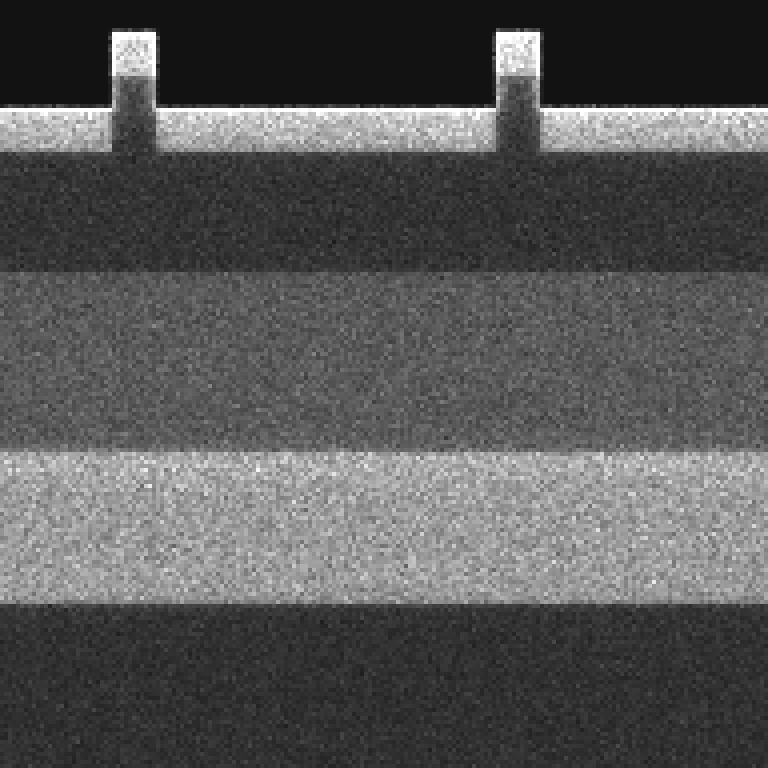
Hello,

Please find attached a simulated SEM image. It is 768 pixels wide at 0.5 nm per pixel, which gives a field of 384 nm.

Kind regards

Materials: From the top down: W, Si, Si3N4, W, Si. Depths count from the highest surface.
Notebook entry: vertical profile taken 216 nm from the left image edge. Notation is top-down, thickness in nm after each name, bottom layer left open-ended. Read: empty 38, W 22, Si 60, Si3N4 90, W 76, Si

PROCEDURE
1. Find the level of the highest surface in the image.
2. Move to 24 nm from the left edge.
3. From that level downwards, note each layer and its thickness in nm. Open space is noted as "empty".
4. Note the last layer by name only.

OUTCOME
empty 38, W 22, Si 60, Si3N4 90, W 76, Si